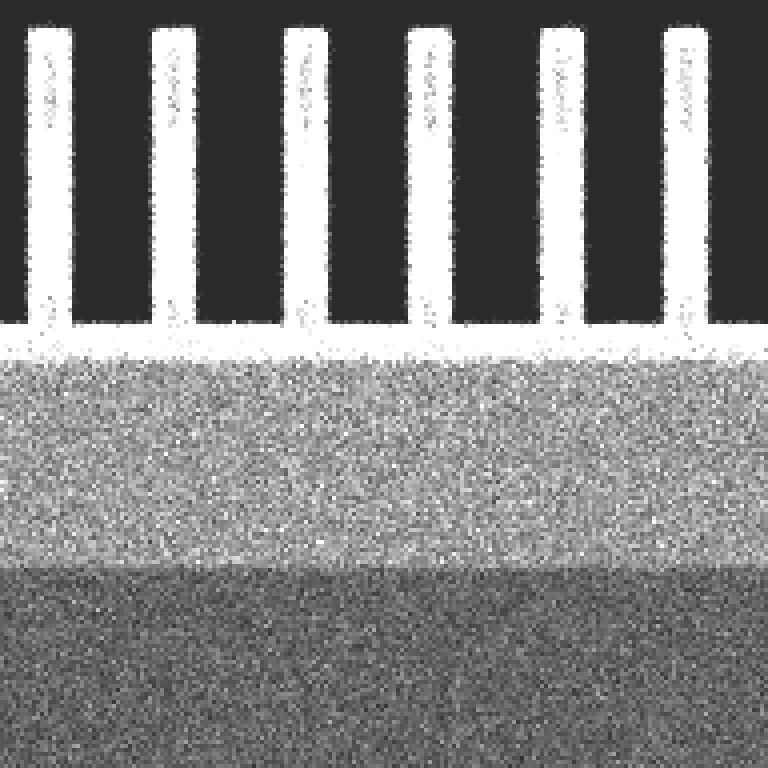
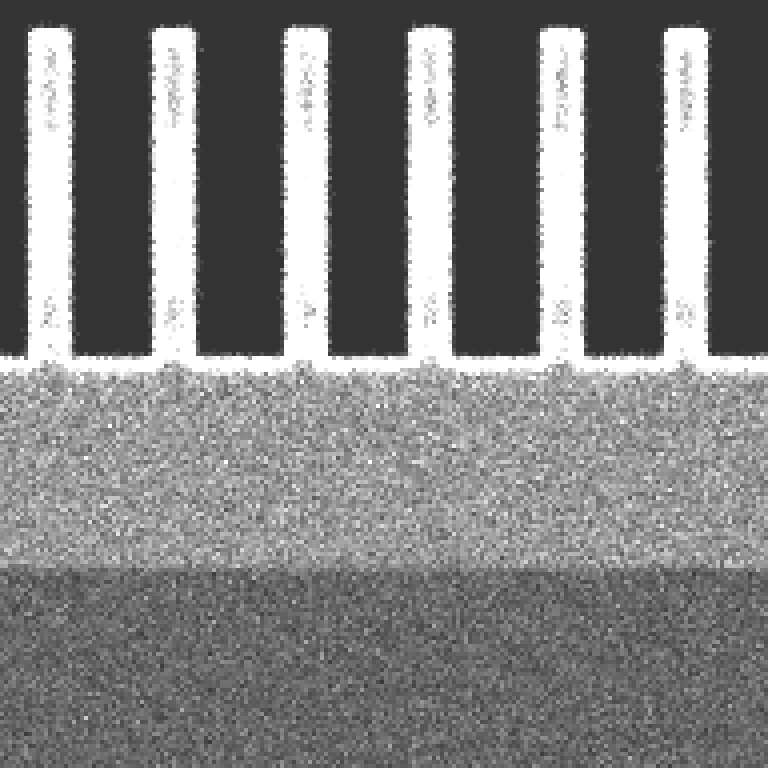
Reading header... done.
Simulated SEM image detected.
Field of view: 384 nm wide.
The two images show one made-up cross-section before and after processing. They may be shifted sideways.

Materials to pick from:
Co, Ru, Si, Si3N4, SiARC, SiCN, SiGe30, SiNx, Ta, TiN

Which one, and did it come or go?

Co - removed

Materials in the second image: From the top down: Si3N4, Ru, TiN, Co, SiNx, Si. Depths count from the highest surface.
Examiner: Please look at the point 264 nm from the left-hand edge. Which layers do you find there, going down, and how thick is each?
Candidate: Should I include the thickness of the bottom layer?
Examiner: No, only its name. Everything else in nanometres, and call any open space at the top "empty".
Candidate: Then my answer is empty 164, SiNx 104, Si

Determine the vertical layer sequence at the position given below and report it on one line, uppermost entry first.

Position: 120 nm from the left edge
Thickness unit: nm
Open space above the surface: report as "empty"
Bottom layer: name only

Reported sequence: empty 164, SiNx 104, Si